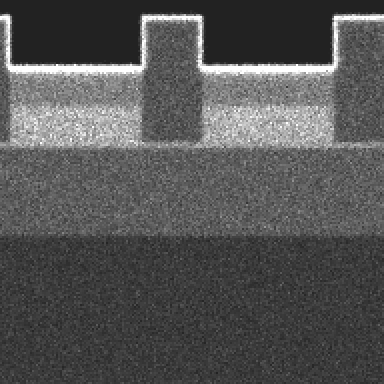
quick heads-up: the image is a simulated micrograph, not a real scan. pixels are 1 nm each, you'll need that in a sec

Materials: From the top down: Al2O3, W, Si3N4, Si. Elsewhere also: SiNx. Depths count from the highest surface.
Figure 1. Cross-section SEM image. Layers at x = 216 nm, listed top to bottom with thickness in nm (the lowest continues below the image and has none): empty 50, Al2O3 40, W 42, Si3N4 88, Si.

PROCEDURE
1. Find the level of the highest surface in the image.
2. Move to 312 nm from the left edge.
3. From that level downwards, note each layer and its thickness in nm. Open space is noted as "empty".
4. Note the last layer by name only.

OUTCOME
empty 50, Al2O3 40, W 42, Si3N4 88, Si